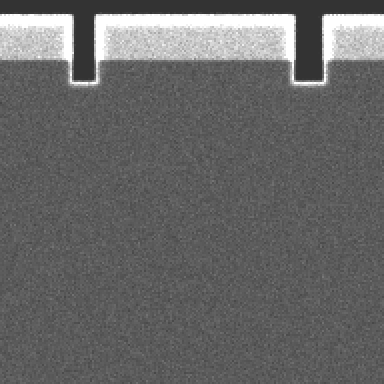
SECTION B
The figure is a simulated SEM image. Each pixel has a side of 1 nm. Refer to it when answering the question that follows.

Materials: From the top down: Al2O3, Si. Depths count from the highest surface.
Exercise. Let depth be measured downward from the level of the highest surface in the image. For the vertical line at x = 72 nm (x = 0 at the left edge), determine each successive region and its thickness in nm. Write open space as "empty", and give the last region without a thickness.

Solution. empty 66, Si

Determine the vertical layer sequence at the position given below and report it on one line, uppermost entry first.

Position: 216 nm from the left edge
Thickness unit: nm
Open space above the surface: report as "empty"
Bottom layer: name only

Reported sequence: Al2O3 44, Si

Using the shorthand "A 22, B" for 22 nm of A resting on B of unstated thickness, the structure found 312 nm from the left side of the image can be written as empty 66, Si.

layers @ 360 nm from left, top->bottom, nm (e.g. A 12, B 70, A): Al2O3 44, Si